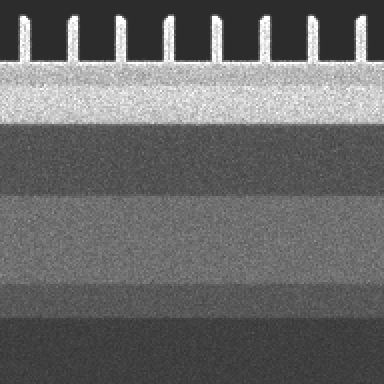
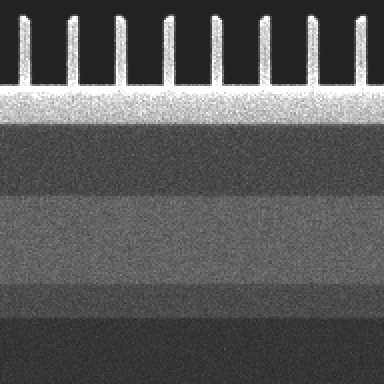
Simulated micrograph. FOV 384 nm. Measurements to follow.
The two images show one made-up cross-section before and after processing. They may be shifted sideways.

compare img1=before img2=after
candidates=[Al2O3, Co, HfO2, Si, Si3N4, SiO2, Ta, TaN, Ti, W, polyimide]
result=removed:W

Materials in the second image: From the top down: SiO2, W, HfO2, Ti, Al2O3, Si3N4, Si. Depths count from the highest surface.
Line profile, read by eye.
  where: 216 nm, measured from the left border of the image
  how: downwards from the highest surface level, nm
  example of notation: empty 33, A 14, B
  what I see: SiO2 46, W 24, HfO2 38, Ti 72, Al2O3 88, Si3N4 34, Si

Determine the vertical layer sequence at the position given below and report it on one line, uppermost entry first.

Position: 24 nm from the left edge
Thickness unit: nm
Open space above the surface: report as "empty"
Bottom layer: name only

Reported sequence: SiO2 46, W 24, HfO2 38, Ti 72, Al2O3 88, Si3N4 34, Si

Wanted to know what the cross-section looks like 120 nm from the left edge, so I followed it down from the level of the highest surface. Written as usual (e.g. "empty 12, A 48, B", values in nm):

SiO2 46, W 24, HfO2 38, Ti 72, Al2O3 88, Si3N4 34, Si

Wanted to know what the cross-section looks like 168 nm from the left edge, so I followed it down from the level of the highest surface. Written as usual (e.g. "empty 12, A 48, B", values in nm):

SiO2 46, W 24, HfO2 38, Ti 72, Al2O3 88, Si3N4 34, Si